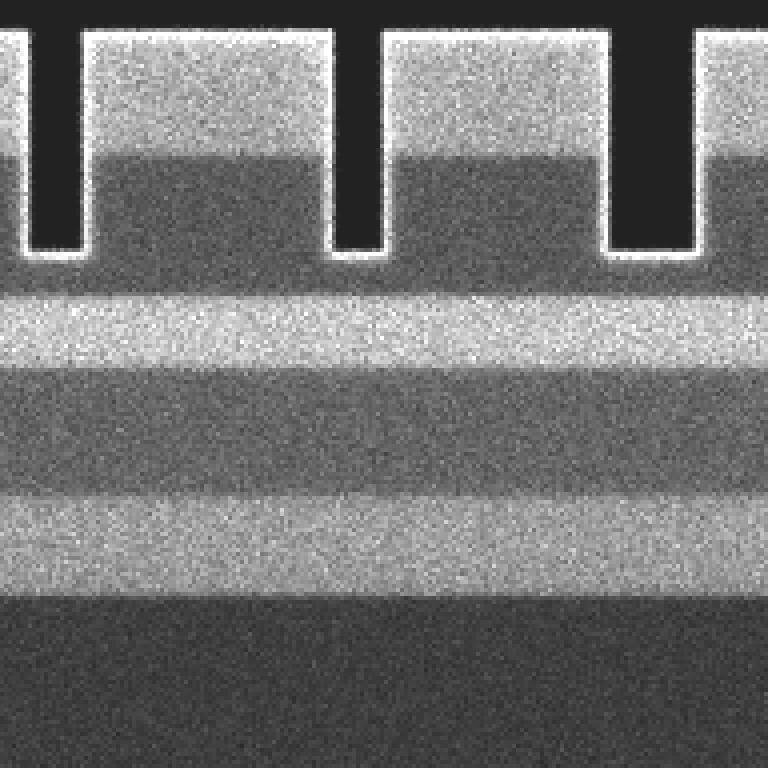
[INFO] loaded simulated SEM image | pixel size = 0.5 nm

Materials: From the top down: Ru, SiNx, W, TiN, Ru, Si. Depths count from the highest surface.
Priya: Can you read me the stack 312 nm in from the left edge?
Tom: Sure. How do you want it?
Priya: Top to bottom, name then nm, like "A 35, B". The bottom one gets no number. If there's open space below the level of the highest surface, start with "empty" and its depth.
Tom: empty 110, SiNx 22, W 36, TiN 64, Ru 50, Si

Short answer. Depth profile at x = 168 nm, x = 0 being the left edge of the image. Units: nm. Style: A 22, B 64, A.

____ empty 110, SiNx 22, W 36, TiN 64, Ru 50, Si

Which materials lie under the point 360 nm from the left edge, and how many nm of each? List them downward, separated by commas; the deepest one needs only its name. Ru 62, SiNx 70, W 36, TiN 64, Ru 50, Si